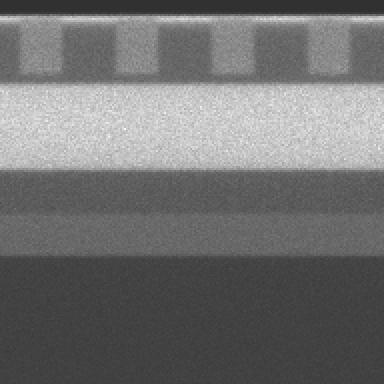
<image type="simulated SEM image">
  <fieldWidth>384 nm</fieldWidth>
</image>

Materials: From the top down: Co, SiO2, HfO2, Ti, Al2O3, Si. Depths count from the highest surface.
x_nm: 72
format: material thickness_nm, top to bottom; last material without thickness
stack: SiO2 68, HfO2 86, Ti 44, Al2O3 42, Si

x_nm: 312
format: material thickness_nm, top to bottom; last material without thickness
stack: Co 58, SiO2 10, HfO2 86, Ti 44, Al2O3 42, Si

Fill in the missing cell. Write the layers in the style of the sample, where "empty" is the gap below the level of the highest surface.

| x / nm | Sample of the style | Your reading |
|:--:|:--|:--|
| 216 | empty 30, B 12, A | Co 58, SiO2 10, HfO2 86, Ti 44, Al2O3 42, Si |